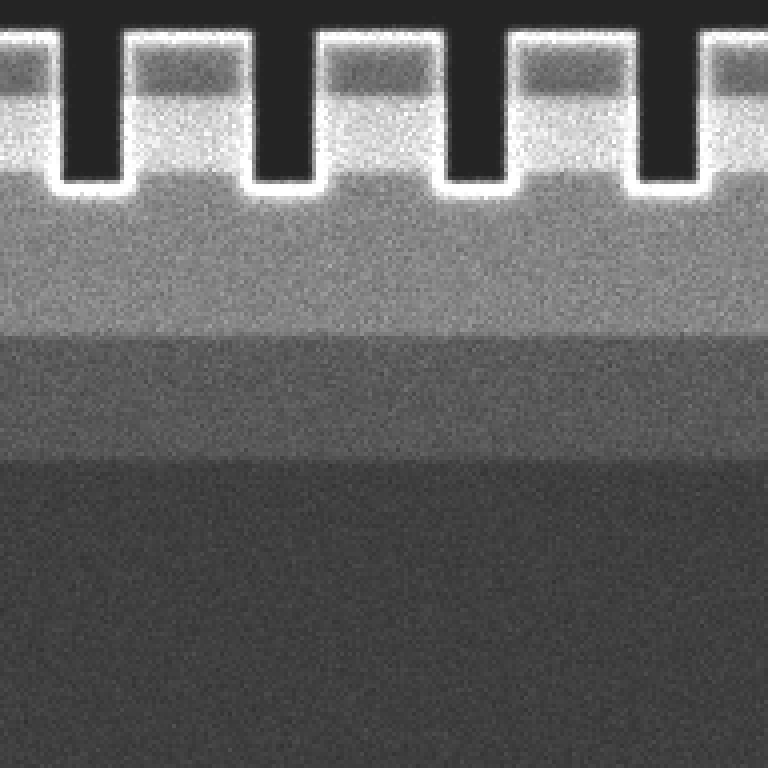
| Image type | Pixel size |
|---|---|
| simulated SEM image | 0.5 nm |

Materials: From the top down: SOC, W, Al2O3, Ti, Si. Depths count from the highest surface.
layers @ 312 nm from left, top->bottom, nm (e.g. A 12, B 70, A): SOC 32, W 38, Al2O3 82, Ti 62, Si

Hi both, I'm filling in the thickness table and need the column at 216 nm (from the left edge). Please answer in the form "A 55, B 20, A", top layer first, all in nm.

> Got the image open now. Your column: SOC 32, W 38, Al2O3 82, Ti 62, Si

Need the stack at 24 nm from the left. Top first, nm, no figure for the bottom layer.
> SOC 32, W 38, Al2O3 82, Ti 62, Si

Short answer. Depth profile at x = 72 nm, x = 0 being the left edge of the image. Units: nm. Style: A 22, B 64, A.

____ SOC 32, W 38, Al2O3 82, Ti 62, Si